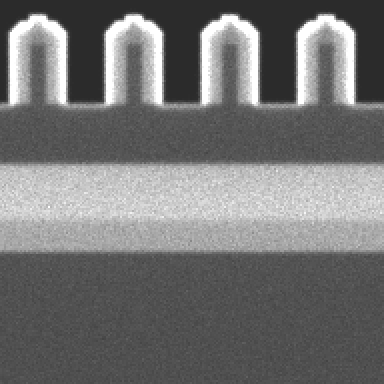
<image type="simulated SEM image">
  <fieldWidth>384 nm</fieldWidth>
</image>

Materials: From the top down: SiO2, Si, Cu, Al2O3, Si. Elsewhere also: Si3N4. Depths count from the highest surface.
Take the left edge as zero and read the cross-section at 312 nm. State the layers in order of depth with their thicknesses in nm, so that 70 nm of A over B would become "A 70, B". empty 6, SiO2 82, Si 60, Cu 56, Al2O3 32, Si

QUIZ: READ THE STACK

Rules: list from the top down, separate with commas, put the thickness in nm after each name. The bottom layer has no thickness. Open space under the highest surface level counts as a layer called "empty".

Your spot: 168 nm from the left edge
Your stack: empty 88, Si 60, Cu 56, Al2O3 32, Si